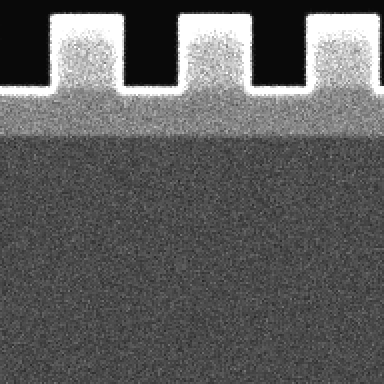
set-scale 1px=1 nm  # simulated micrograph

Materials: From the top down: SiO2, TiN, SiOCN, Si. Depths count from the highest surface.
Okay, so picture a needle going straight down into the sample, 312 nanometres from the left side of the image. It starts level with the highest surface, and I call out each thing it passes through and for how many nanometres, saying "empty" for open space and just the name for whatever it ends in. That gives SiO2 24, TiN 48, SiOCN 48, Si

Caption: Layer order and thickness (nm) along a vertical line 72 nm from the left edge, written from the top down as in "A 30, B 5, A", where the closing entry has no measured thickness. SiO2 24, TiN 48, SiOCN 48, Si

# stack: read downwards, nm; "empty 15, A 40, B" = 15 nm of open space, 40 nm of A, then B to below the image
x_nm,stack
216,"SiO2 24, TiN 48, SiOCN 48, Si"